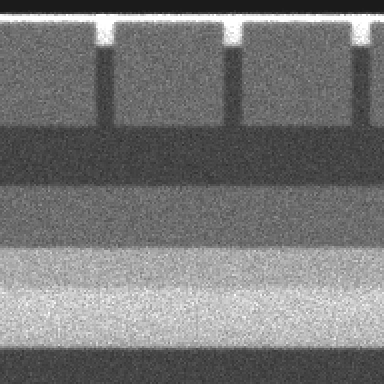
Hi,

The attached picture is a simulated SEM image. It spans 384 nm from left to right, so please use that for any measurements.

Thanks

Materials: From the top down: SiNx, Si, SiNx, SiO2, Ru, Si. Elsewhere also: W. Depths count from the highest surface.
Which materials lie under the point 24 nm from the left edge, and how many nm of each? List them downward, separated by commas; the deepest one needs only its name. SiNx 110, Si 60, SiNx 62, SiO2 40, Ru 60, Si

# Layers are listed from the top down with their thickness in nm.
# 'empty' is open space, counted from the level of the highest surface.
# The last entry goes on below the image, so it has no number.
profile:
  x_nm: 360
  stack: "W 30, Si 140, SiNx 62, SiO2 40, Ru 60, Si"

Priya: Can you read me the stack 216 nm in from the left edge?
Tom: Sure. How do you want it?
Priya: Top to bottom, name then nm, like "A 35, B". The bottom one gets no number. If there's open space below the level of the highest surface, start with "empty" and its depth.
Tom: SiNx 110, Si 60, SiNx 62, SiO2 40, Ru 60, Si